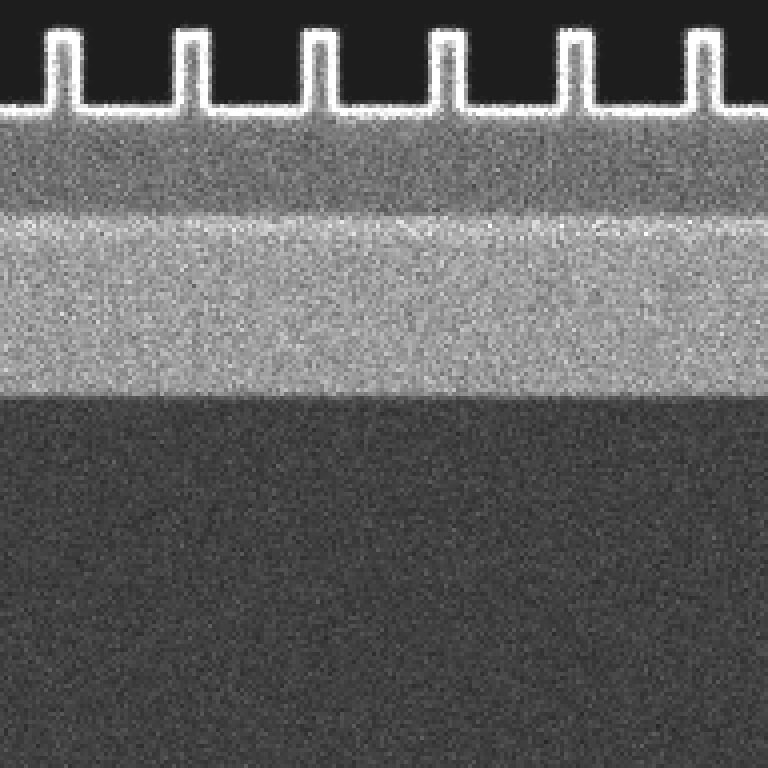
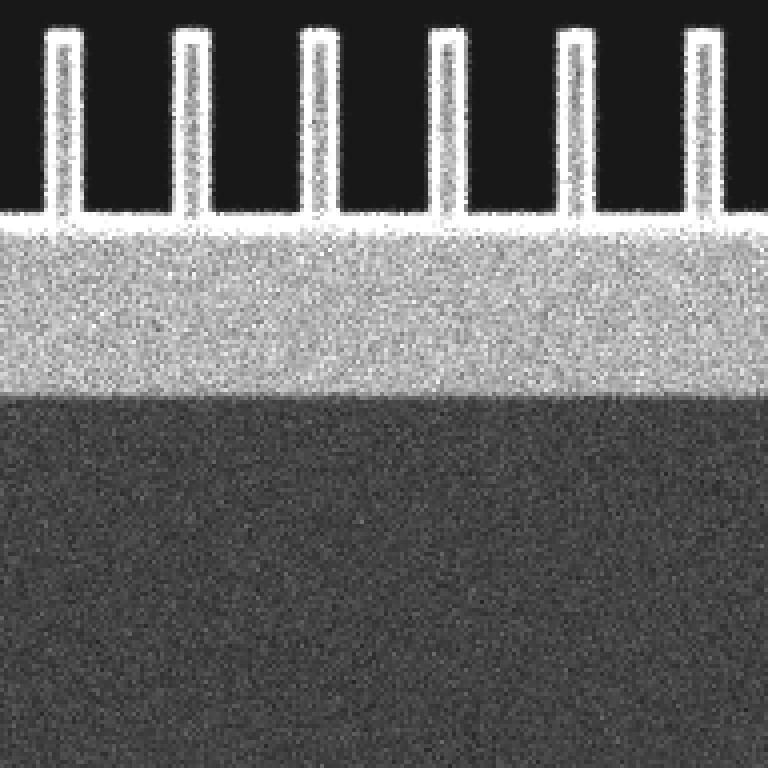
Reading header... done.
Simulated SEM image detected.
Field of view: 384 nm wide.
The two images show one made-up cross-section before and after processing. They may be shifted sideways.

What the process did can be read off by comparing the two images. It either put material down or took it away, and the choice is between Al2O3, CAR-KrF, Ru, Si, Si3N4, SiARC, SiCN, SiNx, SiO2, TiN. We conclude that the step removed TiN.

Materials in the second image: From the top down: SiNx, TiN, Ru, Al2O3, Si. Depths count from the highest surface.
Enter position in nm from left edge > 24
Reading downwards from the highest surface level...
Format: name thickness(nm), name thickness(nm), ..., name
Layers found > SiNx 38, TiN 54, Ru 10, Al2O3 80, Si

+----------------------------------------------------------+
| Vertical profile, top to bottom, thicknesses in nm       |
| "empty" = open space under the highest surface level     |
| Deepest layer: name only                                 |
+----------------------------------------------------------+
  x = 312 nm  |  empty 92, Ru 10, Al2O3 80, Si